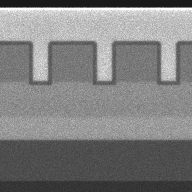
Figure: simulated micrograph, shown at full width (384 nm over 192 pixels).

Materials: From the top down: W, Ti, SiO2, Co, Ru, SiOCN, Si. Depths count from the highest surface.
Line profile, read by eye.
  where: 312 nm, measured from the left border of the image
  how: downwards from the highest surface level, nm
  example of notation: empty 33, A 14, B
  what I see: W 66, Ti 8, SiO2 74, Co 70, Ru 46, SiOCN 82, Si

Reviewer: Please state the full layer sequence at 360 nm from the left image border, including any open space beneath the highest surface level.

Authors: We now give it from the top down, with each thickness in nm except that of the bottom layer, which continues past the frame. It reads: W 66, Ti 8, SiO2 74, Co 70, Ru 46, SiOCN 82, Si